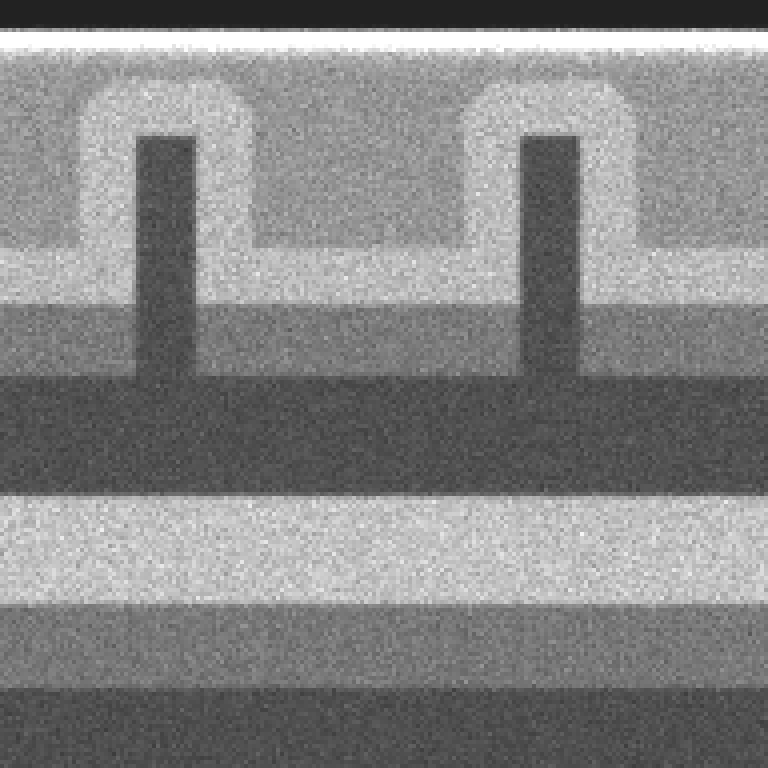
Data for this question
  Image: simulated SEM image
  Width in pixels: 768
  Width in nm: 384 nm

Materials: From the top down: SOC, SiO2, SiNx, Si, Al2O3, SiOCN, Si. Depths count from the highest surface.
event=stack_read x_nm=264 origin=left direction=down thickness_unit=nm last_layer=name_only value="SOC 24, SiO2 28, Si 180, Al2O3 54, SiOCN 42, Si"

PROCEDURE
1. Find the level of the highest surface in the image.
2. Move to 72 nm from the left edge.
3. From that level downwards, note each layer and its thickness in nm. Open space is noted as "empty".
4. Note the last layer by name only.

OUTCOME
SOC 24, SiO2 28, Si 180, Al2O3 54, SiOCN 42, Si